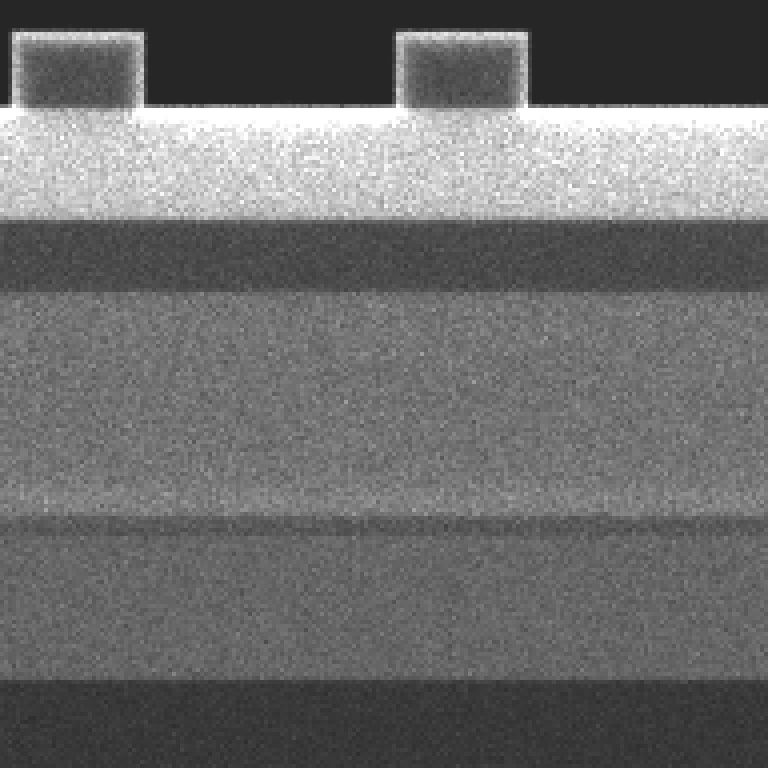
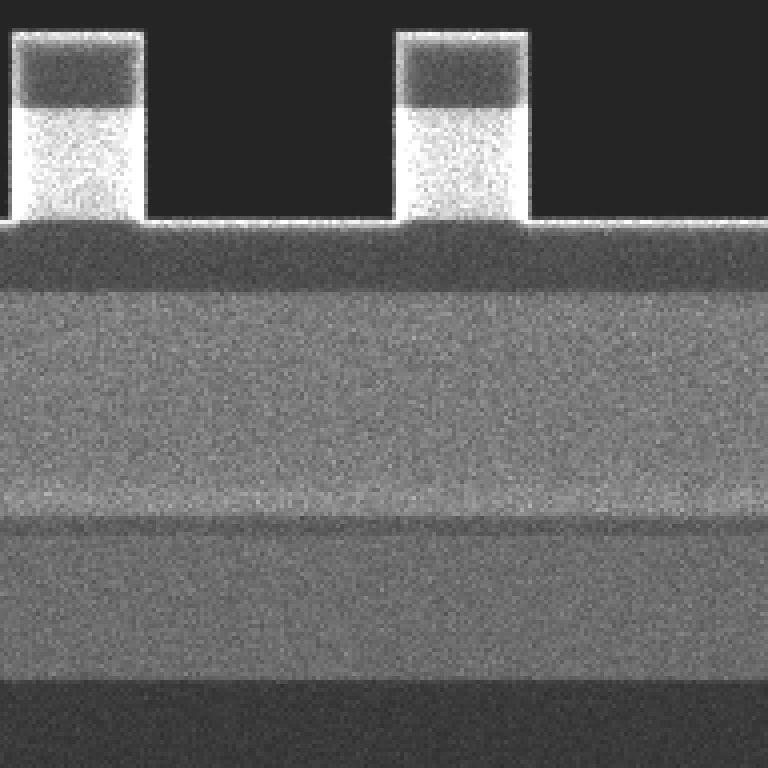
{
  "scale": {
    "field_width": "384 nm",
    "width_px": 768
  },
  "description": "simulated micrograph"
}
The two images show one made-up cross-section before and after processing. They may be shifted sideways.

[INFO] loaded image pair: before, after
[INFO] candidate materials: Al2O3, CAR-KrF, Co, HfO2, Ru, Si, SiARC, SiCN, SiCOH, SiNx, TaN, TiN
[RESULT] removed HfO2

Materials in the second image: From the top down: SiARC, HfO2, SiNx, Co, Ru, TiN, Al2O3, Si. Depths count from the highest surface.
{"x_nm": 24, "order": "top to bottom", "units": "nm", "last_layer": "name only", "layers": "SiARC 38, HfO2 56, SiNx 36, Co 98, Ru 14, TiN 10, Al2O3 72, Si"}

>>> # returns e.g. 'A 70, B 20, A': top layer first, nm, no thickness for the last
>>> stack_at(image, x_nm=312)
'empty 94, SiNx 36, Co 98, Ru 14, TiN 10, Al2O3 72, Si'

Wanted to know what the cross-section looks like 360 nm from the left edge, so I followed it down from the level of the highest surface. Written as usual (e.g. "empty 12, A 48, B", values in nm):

empty 94, SiNx 36, Co 98, Ru 14, TiN 10, Al2O3 72, Si